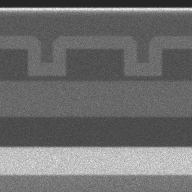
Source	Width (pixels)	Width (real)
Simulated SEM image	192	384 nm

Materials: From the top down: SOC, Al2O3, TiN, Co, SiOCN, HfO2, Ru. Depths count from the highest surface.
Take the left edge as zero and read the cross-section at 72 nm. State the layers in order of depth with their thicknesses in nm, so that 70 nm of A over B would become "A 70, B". SOC 60, Al2O3 76, TiN 10, Co 72, SiOCN 60, HfO2 56, Ru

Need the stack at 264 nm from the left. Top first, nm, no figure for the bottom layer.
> SOC 60, Al2O3 76, TiN 10, Co 72, SiOCN 60, HfO2 56, Ru